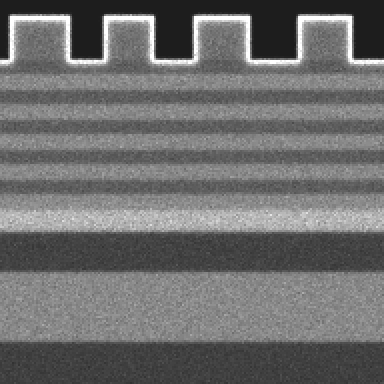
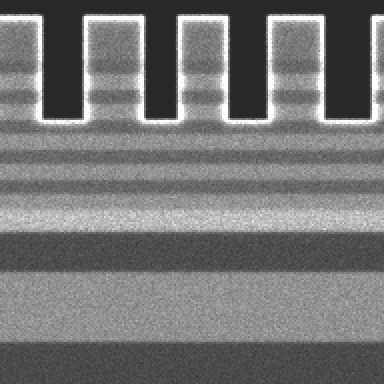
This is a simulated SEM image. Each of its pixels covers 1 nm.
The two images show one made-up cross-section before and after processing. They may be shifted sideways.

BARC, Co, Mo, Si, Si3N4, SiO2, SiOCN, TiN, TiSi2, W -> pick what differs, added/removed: SiO2 and SiOCN removed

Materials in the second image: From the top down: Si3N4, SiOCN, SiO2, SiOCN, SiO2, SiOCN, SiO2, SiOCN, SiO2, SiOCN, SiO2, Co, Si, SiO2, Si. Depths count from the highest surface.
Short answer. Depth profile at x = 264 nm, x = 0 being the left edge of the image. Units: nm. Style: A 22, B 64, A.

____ empty 104, SiOCN 14, SiO2 16, SiOCN 14, SiO2 16, SiOCN 14, SiO2 16, Co 22, Si 40, SiO2 70, Si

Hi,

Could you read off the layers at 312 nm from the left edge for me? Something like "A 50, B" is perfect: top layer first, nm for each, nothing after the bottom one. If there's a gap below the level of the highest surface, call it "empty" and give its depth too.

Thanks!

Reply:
Si3N4 44, SiOCN 14, SiO2 16, SiOCN 14, SiO2 16, SiOCN 14, SiO2 16, SiOCN 14, SiO2 16, SiOCN 14, SiO2 16, Co 22, Si 40, SiO2 70, Si